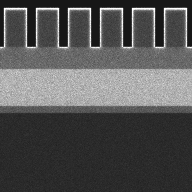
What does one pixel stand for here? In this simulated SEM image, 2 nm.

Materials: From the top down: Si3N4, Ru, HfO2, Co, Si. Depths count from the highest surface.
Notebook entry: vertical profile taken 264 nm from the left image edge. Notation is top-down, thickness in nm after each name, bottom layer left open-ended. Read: Si3N4 78, Ru 44, HfO2 74, Co 14, Si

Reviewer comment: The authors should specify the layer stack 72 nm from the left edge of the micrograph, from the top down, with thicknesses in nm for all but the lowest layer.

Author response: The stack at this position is Si3N4 78, Ru 44, HfO2 74, Co 14, Si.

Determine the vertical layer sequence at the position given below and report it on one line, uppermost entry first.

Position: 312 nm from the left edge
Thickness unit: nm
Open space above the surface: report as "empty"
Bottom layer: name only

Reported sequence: empty 78, Ru 44, HfO2 74, Co 14, Si